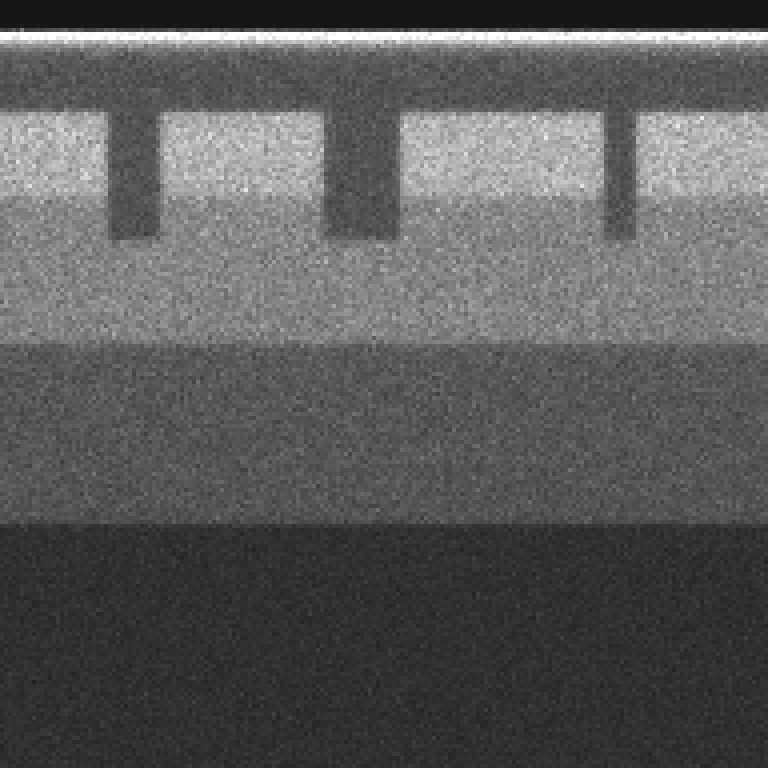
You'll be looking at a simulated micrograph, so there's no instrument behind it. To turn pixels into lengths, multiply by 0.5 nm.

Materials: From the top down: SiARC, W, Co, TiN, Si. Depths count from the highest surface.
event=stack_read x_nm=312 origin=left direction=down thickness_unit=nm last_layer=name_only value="SiARC 104, Co 52, TiN 90, Si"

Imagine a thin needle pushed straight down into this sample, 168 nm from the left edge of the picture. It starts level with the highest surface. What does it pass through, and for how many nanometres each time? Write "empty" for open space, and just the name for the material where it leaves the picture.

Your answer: SiARC 104, Co 52, TiN 90, Si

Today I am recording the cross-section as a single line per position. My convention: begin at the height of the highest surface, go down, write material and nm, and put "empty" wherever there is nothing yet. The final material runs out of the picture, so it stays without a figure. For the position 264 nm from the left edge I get SiARC 40, W 42, Co 74, TiN 90, Si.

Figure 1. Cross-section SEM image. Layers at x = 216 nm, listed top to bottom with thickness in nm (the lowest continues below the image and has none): SiARC 40, W 42, Co 74, TiN 90, Si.